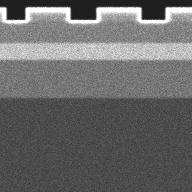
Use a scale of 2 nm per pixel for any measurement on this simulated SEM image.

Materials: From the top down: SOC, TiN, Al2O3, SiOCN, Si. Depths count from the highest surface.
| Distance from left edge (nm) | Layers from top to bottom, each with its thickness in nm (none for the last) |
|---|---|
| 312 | empty 26, TiN 44, Al2O3 34, SiOCN 76, Si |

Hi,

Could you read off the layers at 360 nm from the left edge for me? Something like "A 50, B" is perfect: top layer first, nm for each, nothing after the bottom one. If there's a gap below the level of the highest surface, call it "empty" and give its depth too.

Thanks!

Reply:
SOC 26, TiN 44, Al2O3 34, SiOCN 76, Si